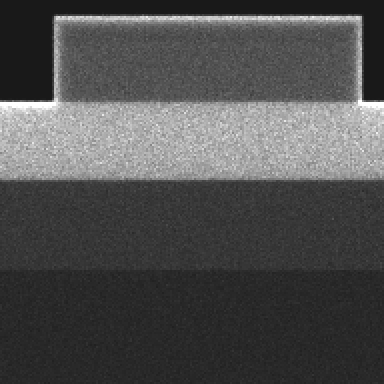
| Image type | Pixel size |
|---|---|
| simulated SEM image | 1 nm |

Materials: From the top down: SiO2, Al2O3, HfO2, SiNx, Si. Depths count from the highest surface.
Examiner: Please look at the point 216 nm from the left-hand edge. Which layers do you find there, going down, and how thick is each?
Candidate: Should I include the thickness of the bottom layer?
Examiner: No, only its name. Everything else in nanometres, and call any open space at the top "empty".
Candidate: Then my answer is SiO2 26, Al2O3 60, HfO2 78, SiNx 90, Si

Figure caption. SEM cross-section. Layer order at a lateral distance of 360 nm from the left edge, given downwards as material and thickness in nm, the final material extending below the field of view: SiO2 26, Al2O3 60, HfO2 78, SiNx 90, Si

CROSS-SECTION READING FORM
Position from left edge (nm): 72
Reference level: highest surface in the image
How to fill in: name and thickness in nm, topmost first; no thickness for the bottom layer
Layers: SiO2 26, Al2O3 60, HfO2 78, SiNx 90, Si